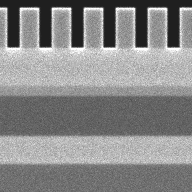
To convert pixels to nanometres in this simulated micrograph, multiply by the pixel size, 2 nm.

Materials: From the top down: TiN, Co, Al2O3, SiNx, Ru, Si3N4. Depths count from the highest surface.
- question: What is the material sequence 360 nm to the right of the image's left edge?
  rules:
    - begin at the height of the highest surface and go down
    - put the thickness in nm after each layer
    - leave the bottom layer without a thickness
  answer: TiN 80, Co 76, Al2O3 20, SiNx 80, Ru 56, Si3N4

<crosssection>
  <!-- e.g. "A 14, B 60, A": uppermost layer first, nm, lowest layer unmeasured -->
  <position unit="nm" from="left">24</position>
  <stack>empty 80, Co 76, Al2O3 20, SiNx 80, Ru 56, Si3N4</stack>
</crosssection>